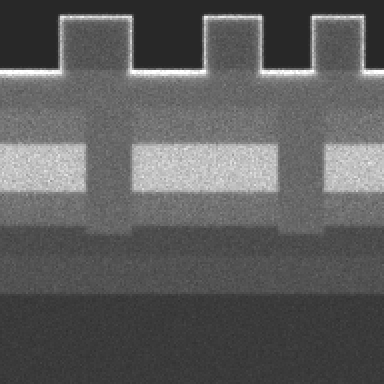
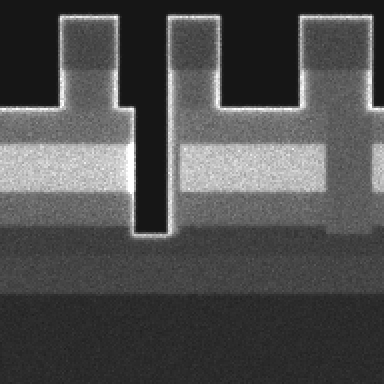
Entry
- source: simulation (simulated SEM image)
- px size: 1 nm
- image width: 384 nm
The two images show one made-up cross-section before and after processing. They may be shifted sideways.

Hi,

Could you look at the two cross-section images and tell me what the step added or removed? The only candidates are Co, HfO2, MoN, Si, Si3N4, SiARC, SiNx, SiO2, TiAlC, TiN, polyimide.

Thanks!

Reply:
removed SiO2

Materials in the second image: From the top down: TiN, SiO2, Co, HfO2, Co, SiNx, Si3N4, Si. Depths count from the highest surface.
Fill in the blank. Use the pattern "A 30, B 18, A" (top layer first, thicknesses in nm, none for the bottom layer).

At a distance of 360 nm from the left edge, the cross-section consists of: TiN 54, SiO2 164, SiNx 22, Si3N4 38, Si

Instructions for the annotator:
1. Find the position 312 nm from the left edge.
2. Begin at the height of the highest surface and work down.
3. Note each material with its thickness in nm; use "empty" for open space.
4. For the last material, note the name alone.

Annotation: TiN 54, SiO2 38, Co 36, HfO2 48, Co 34, SiNx 30, Si3N4 38, Si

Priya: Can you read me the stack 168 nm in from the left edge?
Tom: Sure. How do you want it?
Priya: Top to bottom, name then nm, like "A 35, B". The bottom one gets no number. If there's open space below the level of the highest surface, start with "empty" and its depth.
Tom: TiN 54, SiO2 164, SiNx 22, Si3N4 38, Si